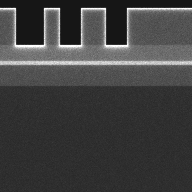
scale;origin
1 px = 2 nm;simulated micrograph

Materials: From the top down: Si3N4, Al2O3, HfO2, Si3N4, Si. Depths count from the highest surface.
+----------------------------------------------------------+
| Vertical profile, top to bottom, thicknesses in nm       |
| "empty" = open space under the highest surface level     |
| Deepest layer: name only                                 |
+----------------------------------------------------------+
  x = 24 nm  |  Si3N4 74, Al2O3 32, HfO2 8, Si3N4 42, Si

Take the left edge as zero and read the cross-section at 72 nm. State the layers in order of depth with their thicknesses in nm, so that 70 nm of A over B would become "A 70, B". empty 74, Al2O3 32, HfO2 8, Si3N4 42, Si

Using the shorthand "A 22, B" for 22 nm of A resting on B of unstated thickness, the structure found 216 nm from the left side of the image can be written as empty 74, Al2O3 32, HfO2 8, Si3N4 42, Si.